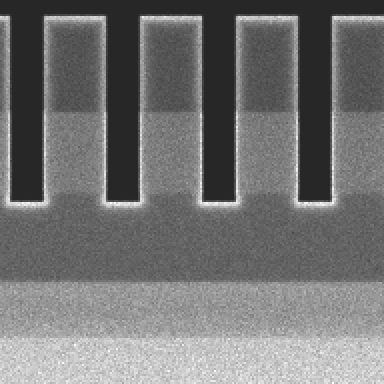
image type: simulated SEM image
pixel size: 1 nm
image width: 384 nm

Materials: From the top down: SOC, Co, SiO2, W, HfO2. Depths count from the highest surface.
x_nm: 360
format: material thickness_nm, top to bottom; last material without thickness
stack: SOC 96, Co 82, SiO2 88, W 56, HfO2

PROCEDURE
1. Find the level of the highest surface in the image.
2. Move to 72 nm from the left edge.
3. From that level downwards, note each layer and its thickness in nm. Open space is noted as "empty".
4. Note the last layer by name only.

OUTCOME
SOC 96, Co 82, SiO2 88, W 56, HfO2